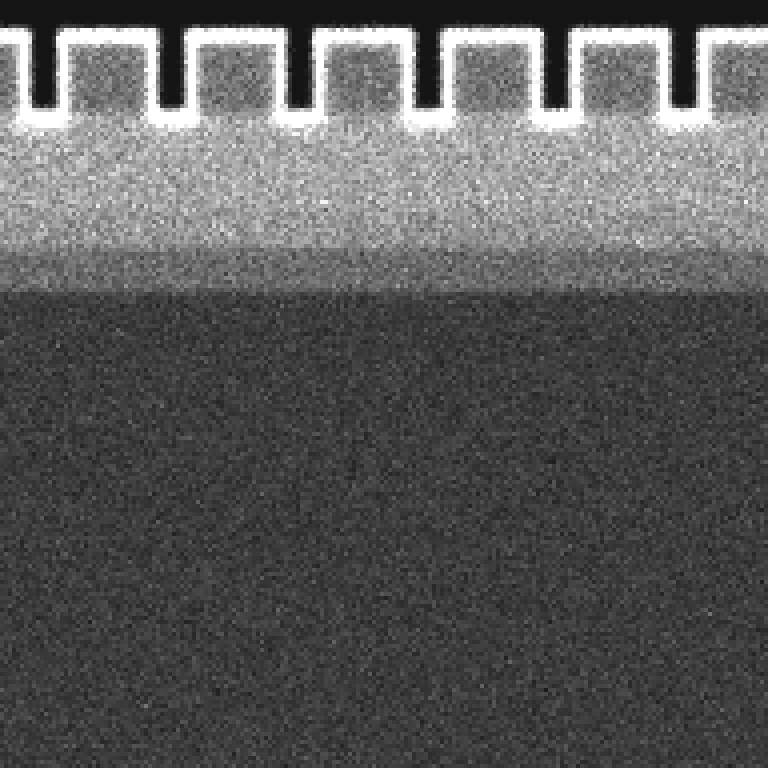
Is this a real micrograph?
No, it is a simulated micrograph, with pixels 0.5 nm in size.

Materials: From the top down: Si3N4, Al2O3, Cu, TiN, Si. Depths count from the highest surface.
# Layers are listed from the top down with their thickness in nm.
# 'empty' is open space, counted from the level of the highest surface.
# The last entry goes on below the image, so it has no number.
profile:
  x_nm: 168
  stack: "Si3N4 40, Al2O3 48, Cu 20, TiN 22, Si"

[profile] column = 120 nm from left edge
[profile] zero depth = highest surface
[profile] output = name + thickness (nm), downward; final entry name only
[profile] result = Si3N4 40, Al2O3 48, Cu 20, TiN 22, Si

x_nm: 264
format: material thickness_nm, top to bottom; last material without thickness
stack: Si3N4 40, Al2O3 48, Cu 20, TiN 22, Si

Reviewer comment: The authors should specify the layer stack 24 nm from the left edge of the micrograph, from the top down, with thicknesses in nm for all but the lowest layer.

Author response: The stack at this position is empty 40, Al2O3 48, Cu 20, TiN 22, Si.